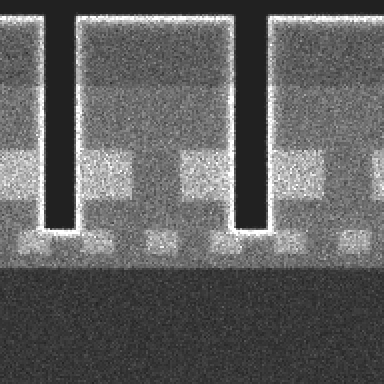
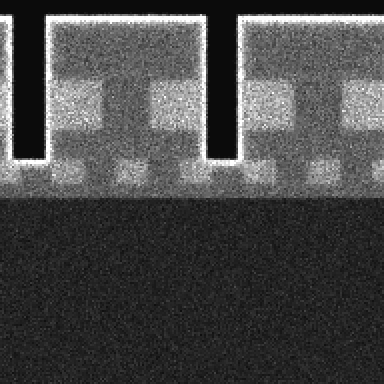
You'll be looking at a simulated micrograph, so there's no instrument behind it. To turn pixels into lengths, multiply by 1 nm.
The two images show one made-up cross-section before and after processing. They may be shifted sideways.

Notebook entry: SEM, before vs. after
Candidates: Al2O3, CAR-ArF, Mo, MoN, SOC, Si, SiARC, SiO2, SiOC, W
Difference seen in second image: SOC removed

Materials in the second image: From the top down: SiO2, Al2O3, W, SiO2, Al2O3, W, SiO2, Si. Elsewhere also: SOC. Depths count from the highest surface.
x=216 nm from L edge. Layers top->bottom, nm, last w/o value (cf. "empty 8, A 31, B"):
empty 144, SiO2 38, Si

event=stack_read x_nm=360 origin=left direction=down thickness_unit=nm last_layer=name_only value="SiO2 54, Al2O3 10, W 50, SiO2 14, Al2O3 16, SiO2 38, Si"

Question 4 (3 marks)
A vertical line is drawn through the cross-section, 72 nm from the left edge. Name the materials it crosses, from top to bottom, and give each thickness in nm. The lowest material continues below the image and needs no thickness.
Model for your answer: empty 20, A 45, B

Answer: SiO2 54, Al2O3 10, W 50, SiO2 14, Al2O3 16, W 24, SiO2 14, Si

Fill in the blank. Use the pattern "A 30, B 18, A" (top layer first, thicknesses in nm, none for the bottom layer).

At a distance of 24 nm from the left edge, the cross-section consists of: empty 144, SiO2 38, Si